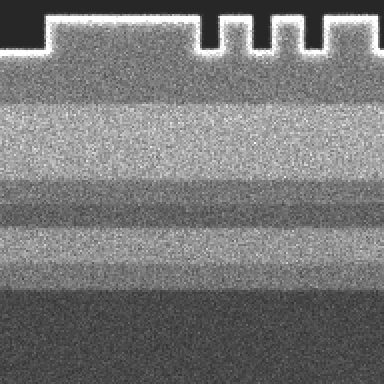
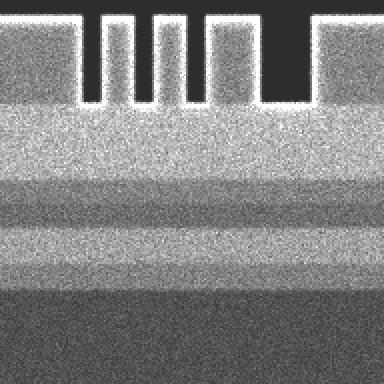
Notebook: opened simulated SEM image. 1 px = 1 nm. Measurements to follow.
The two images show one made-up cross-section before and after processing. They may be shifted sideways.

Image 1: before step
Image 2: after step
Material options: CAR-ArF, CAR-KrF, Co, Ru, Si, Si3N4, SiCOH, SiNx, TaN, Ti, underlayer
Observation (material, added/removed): underlayer, removed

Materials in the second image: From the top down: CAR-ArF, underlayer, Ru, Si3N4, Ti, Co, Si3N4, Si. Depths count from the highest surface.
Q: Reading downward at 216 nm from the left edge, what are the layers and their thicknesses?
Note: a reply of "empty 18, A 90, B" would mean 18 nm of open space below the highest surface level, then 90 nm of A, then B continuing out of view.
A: CAR-ArF 34, underlayer 54, Ru 76, Si3N4 24, Ti 24, Co 36, Si3N4 26, Si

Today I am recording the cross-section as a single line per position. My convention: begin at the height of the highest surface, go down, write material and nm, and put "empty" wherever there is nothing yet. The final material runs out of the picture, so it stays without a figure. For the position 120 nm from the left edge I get CAR-ArF 34, underlayer 54, Ru 76, Si3N4 24, Ti 24, Co 36, Si3N4 26, Si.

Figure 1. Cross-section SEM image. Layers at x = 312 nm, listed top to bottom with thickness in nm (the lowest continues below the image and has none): CAR-ArF 34, underlayer 54, Ru 76, Si3N4 24, Ti 24, Co 36, Si3N4 26, Si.